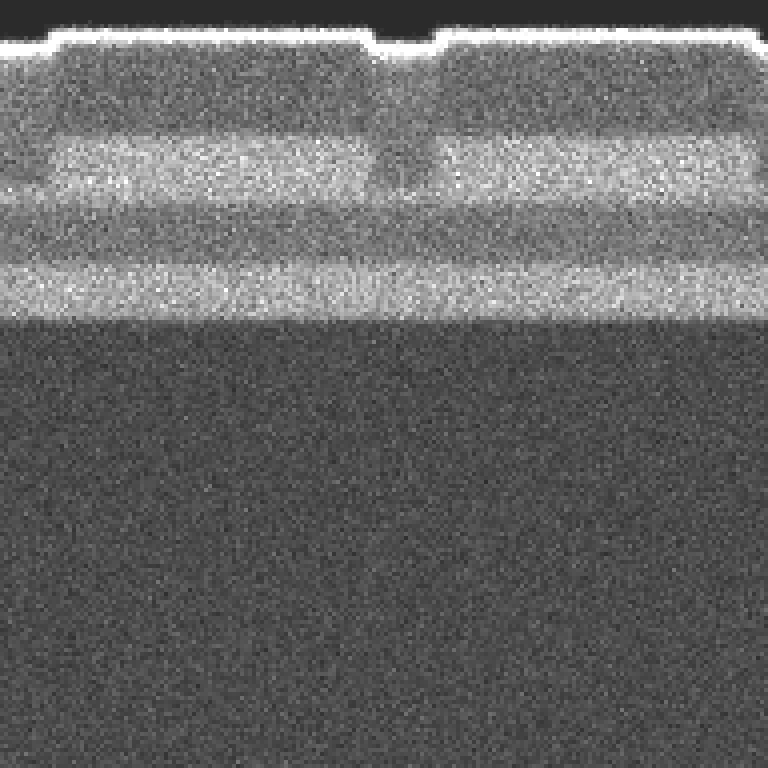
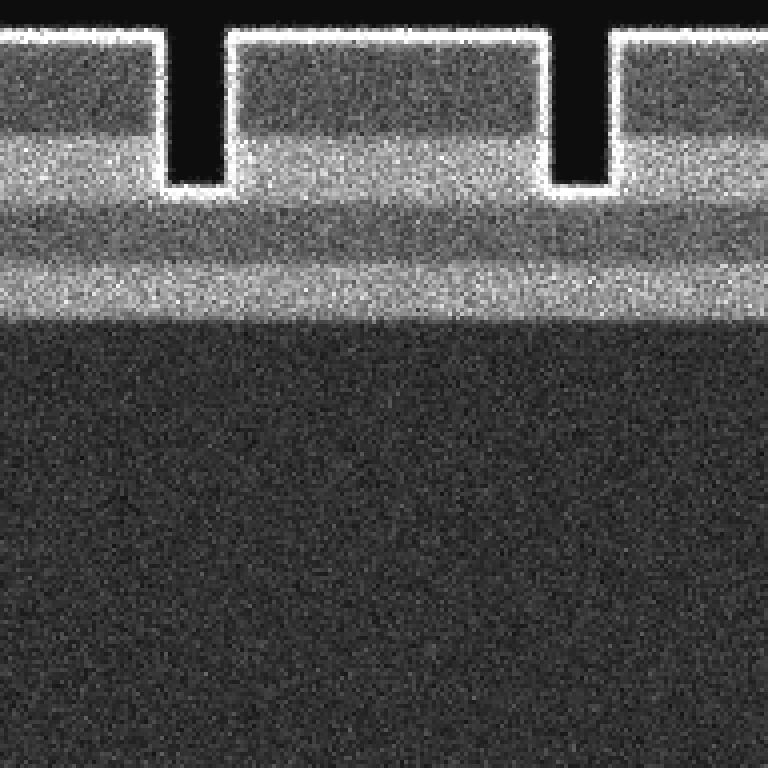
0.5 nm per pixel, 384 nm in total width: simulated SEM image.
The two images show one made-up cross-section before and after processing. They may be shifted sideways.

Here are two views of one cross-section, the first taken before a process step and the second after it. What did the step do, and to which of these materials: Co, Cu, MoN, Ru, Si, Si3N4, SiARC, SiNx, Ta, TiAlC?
It removed SiARC.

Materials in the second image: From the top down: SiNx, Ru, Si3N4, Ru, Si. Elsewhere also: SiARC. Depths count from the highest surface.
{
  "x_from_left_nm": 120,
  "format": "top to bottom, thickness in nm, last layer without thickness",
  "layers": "SiNx 52, Ru 34, Si3N4 30, Ru 28, Si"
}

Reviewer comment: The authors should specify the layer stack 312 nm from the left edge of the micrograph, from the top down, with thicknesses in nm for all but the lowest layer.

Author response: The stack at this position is SiNx 52, Ru 34, Si3N4 30, Ru 28, Si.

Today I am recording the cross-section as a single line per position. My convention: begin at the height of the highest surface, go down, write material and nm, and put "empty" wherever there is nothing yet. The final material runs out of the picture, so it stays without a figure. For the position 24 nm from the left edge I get SiNx 52, Ru 34, Si3N4 30, Ru 28, Si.